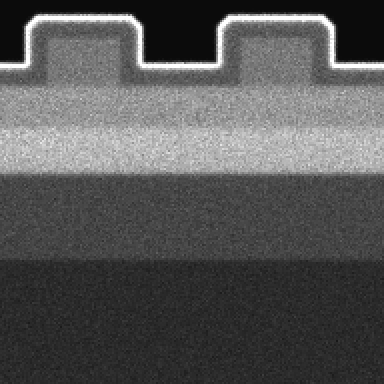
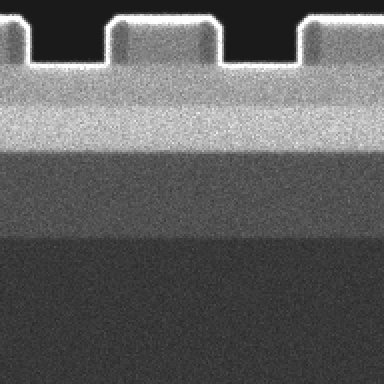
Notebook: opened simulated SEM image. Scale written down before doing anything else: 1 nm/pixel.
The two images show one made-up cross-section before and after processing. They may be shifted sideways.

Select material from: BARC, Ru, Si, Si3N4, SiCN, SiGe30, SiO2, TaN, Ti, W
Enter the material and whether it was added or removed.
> Si3N4 / removed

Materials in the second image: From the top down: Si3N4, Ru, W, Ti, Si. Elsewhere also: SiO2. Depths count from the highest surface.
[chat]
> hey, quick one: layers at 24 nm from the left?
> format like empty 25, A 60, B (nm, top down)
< empty 6, Si3N4 42, Ru 42, W 46, Ti 86, Si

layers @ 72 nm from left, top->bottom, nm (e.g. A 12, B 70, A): empty 48, Ru 42, W 46, Ti 86, Si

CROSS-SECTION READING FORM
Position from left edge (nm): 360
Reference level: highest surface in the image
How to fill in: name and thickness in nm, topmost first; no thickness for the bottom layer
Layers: SiO2 48, Ru 42, W 46, Ti 86, Si